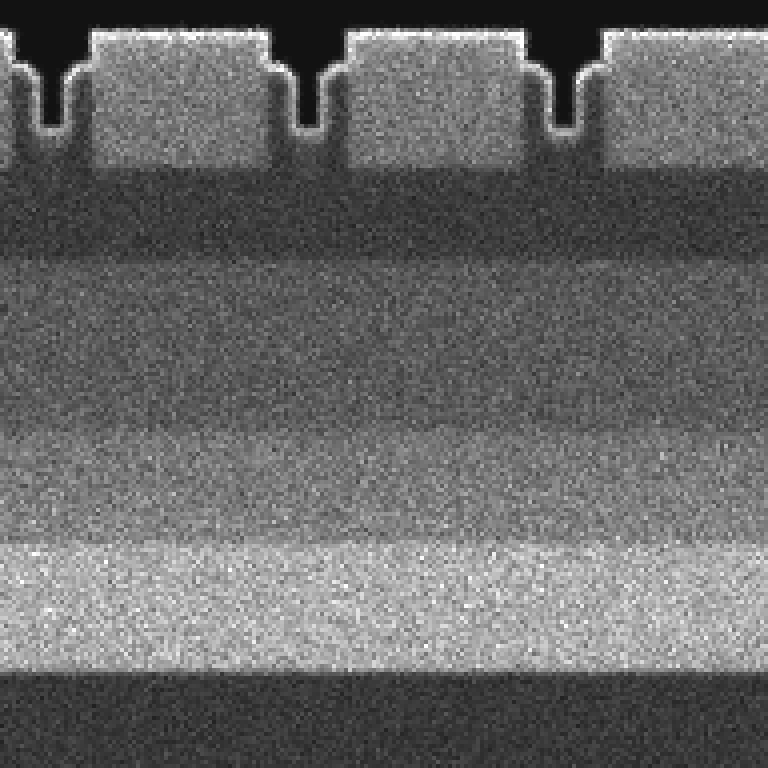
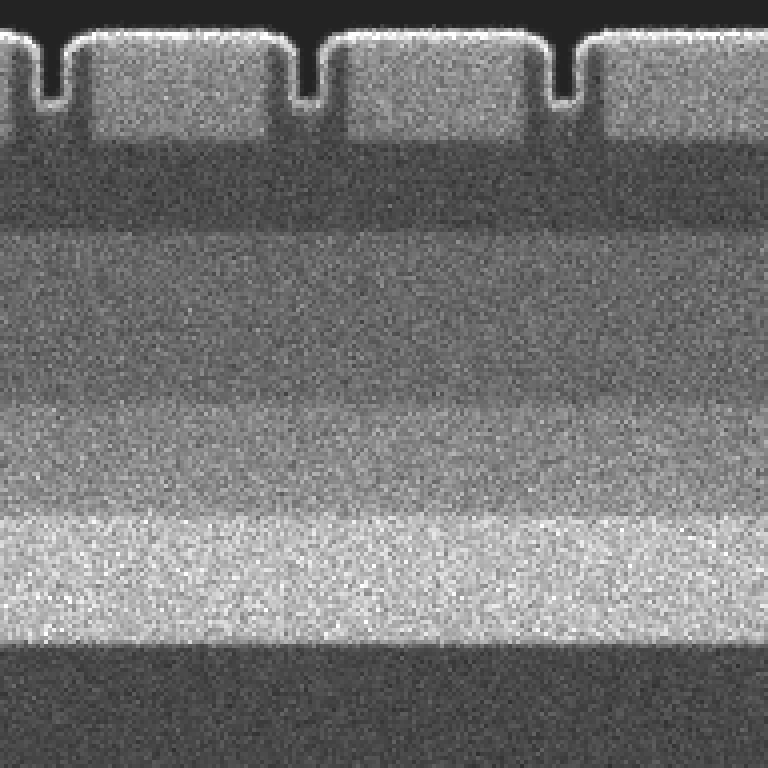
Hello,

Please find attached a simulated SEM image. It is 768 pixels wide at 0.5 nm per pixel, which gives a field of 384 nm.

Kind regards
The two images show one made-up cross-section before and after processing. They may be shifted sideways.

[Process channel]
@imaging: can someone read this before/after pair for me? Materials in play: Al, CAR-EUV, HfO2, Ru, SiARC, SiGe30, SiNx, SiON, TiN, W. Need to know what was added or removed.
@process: W removed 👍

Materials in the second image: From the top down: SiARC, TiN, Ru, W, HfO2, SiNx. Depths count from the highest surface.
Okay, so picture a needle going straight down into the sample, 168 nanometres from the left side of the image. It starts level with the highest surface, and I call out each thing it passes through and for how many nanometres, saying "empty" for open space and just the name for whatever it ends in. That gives empty 2, SiNx 60, TiN 38, Ru 86, W 56, HfO2 64, SiNx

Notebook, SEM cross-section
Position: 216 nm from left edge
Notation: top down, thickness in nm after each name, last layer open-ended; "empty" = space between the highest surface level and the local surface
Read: W 54, TiN 46, Ru 86, W 56, HfO2 64, SiNx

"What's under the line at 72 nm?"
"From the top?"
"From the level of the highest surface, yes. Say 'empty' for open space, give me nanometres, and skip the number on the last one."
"W 54, TiN 46, Ru 86, W 56, HfO2 64, SiNx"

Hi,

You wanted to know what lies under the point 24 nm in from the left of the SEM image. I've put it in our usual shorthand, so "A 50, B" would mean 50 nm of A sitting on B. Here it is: empty 34, SiARC 28, TiN 38, Ru 86, W 56, HfO2 64, SiNx